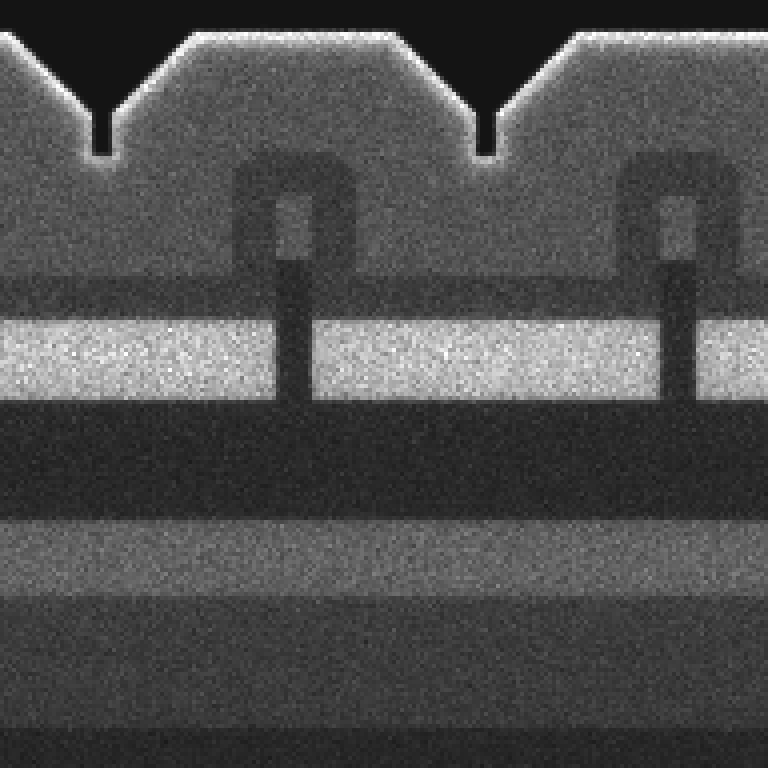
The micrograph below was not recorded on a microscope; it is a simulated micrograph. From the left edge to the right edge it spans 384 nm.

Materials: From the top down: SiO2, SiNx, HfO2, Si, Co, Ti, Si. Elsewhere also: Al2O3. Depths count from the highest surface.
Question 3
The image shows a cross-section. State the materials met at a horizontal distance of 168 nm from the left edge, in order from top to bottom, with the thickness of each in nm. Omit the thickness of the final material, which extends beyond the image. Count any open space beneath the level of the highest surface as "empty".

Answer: SiO2 62, SiNx 82, HfO2 40, Si 60, Co 38, Ti 66, Si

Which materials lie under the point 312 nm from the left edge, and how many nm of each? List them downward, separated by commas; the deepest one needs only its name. SiO2 66, SiNx 78, HfO2 40, Si 60, Co 38, Ti 66, Si